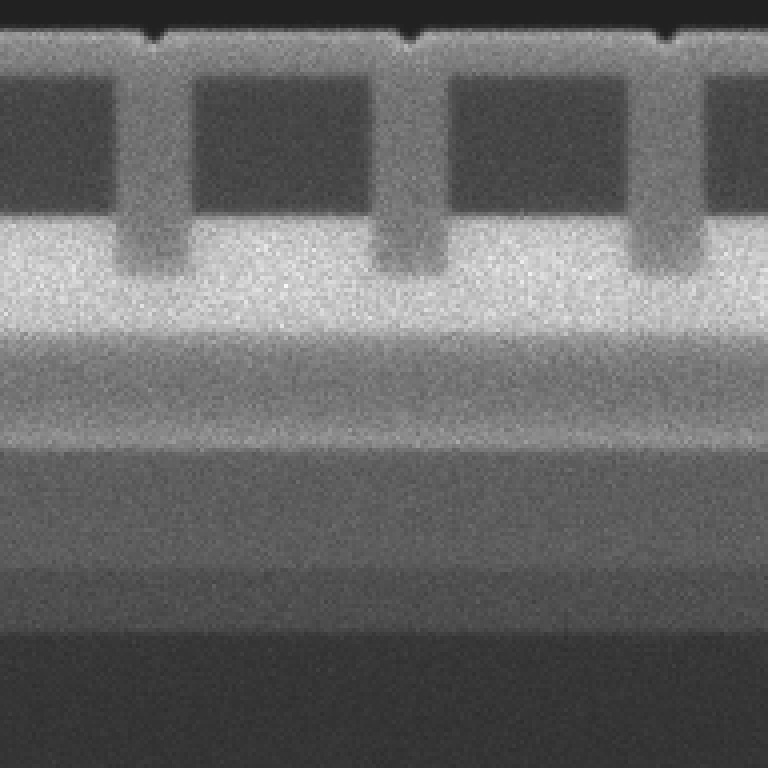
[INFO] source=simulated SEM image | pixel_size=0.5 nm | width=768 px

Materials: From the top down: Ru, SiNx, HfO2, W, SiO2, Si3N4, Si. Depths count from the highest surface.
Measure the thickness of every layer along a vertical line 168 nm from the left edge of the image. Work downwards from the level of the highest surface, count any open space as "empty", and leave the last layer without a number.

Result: Ru 22, SiNx 70, HfO2 58, W 58, SiO2 60, Si3N4 32, Si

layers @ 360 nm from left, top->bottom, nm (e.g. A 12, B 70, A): Ru 22, SiNx 70, HfO2 58, W 58, SiO2 60, Si3N4 32, Si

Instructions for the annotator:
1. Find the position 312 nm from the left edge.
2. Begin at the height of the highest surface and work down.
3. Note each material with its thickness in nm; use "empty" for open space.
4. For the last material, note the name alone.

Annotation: Ru 22, SiNx 70, HfO2 58, W 58, SiO2 60, Si3N4 32, Si